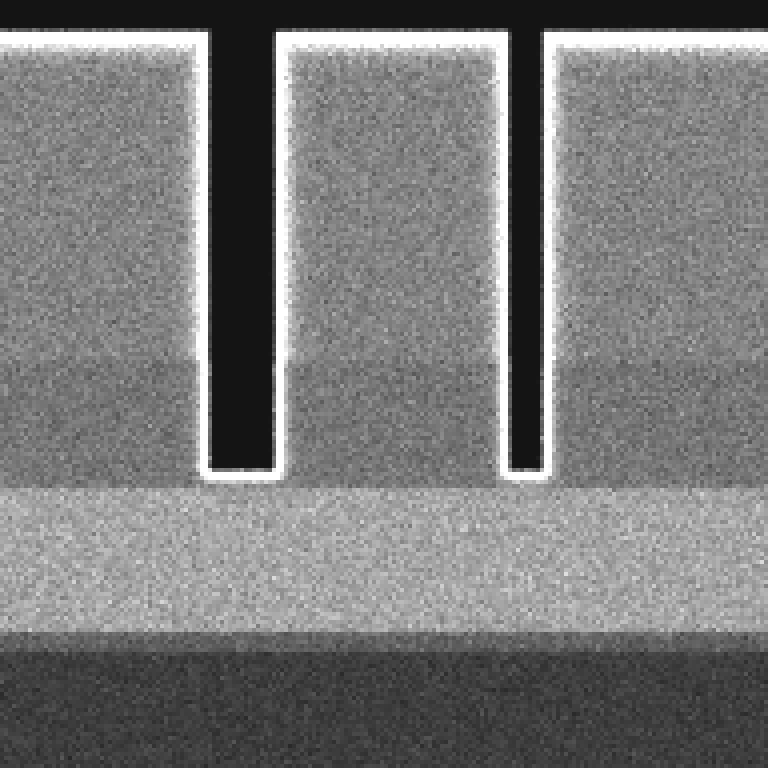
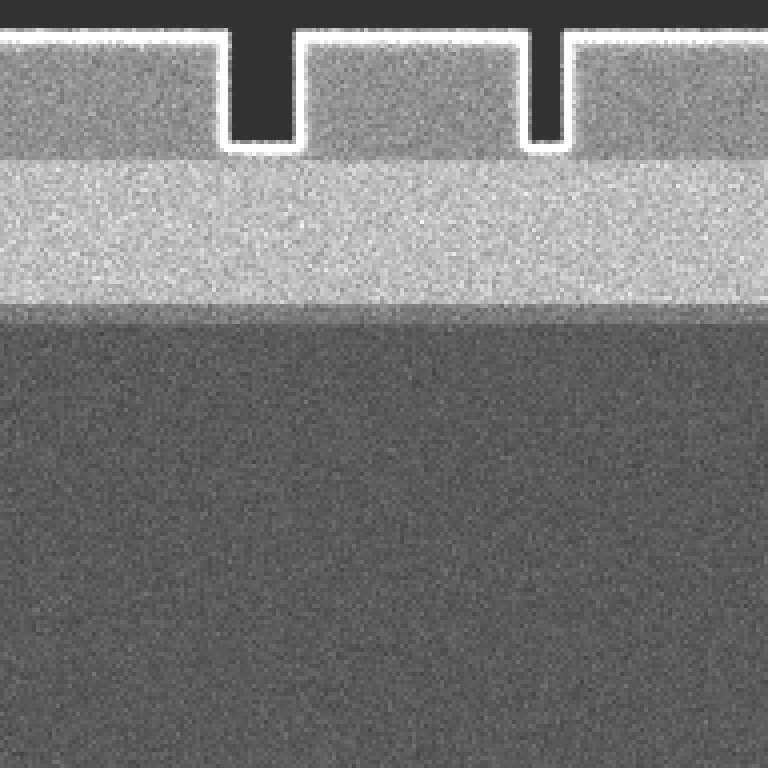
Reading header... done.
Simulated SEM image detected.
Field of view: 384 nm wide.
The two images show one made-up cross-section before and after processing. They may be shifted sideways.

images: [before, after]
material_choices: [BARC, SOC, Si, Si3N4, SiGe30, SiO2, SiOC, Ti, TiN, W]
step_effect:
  removed: SOC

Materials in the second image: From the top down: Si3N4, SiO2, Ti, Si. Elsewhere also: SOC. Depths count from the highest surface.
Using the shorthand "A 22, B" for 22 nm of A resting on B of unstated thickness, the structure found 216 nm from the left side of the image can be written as Si3N4 64, SiO2 72, Ti 10, Si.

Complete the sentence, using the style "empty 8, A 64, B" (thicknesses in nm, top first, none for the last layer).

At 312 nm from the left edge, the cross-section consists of Si3N4 64, SiO2 72, Ti 10, Si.